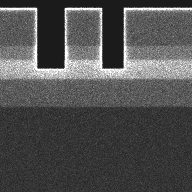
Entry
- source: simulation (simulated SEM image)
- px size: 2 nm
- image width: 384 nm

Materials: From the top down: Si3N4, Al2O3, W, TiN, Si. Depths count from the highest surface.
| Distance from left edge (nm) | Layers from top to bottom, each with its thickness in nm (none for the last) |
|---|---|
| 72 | Si3N4 76, Al2O3 28, W 38, TiN 56, Si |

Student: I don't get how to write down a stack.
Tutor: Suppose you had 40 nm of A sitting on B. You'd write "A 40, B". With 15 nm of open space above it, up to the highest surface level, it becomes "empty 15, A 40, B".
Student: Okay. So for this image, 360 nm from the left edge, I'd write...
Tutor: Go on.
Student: Si3N4 76, Al2O3 28, W 38, TiN 56, Si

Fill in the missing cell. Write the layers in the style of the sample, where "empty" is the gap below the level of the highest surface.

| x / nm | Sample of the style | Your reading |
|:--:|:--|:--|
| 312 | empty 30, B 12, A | Si3N4 76, Al2O3 28, W 38, TiN 56, Si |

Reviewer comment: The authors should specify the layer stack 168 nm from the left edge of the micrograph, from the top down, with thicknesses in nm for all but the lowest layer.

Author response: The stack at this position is Si3N4 76, Al2O3 28, W 38, TiN 56, Si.